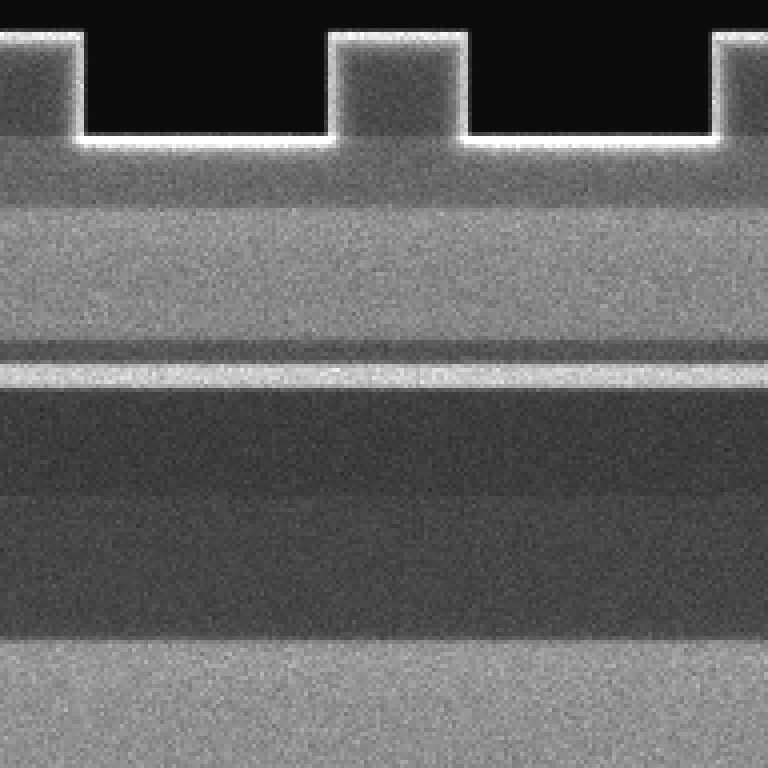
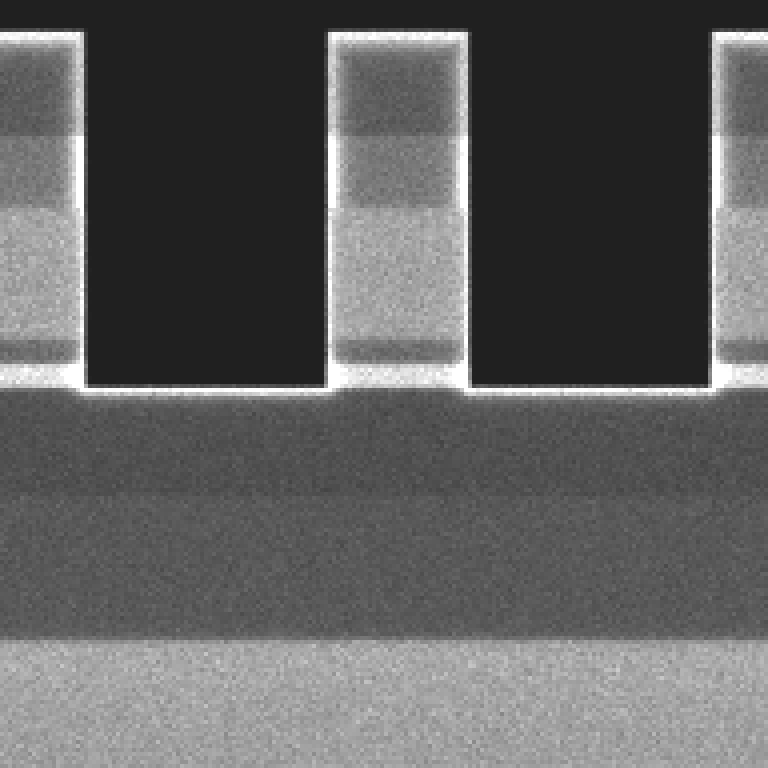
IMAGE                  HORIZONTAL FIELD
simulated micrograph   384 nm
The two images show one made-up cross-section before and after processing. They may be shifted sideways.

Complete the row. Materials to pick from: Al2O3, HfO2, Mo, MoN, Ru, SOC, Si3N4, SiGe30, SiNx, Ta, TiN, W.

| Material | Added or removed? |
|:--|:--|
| Al2O3 and HfO2 and Ru and TiN | removed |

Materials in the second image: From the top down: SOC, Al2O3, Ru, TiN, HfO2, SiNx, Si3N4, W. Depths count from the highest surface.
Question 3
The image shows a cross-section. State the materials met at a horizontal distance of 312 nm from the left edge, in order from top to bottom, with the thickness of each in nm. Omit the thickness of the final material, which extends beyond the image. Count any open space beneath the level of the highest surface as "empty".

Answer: empty 178, SiNx 54, Si3N4 72, W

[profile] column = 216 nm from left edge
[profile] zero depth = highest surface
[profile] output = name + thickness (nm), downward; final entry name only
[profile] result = SOC 52, Al2O3 36, Ru 66, TiN 12, HfO2 12, SiNx 54, Si3N4 72, W